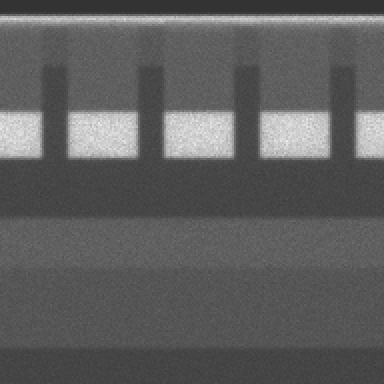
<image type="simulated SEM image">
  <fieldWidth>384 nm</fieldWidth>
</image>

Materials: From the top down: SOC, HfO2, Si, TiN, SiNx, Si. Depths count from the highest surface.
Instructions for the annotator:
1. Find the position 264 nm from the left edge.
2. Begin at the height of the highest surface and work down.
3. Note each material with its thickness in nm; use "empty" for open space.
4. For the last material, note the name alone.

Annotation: SOC 96, HfO2 46, Si 60, TiN 50, SiNx 80, Si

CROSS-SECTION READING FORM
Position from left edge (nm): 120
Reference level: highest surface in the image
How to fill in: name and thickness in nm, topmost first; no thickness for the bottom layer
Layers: SOC 96, HfO2 46, Si 60, TiN 50, SiNx 80, Si